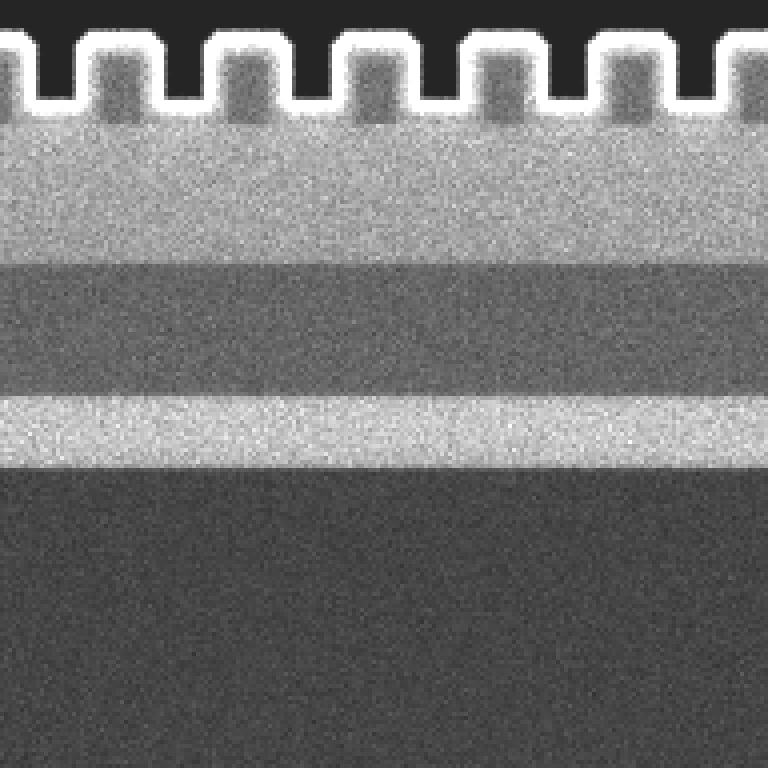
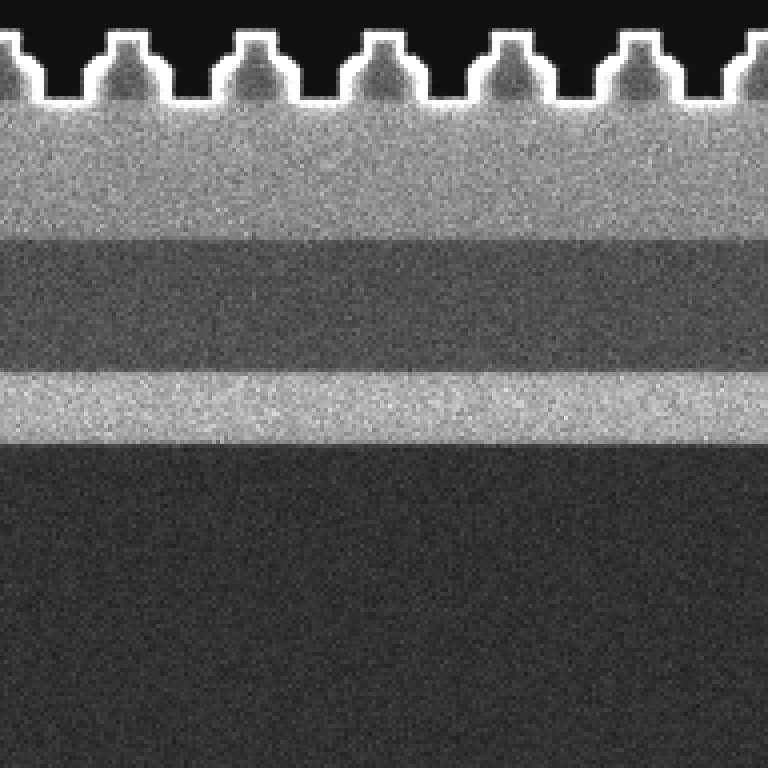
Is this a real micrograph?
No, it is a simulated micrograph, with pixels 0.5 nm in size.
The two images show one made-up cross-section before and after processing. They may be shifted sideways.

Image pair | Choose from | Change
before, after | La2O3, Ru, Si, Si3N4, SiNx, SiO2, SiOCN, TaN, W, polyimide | SiO2 (removed)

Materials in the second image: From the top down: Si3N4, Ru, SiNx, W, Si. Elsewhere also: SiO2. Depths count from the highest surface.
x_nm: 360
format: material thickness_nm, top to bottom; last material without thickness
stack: empty 34, Ru 70, SiNx 66, W 36, Si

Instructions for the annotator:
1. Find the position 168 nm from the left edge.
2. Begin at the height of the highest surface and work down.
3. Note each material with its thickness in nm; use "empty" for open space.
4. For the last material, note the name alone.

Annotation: empty 34, Ru 70, SiNx 66, W 36, Si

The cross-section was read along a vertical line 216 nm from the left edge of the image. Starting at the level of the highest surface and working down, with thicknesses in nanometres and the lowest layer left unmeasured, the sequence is empty 34, Ru 70, SiNx 66, W 36, Si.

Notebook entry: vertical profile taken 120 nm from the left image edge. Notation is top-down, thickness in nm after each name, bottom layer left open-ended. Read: Si3N4 34, Ru 70, SiNx 66, W 36, Si